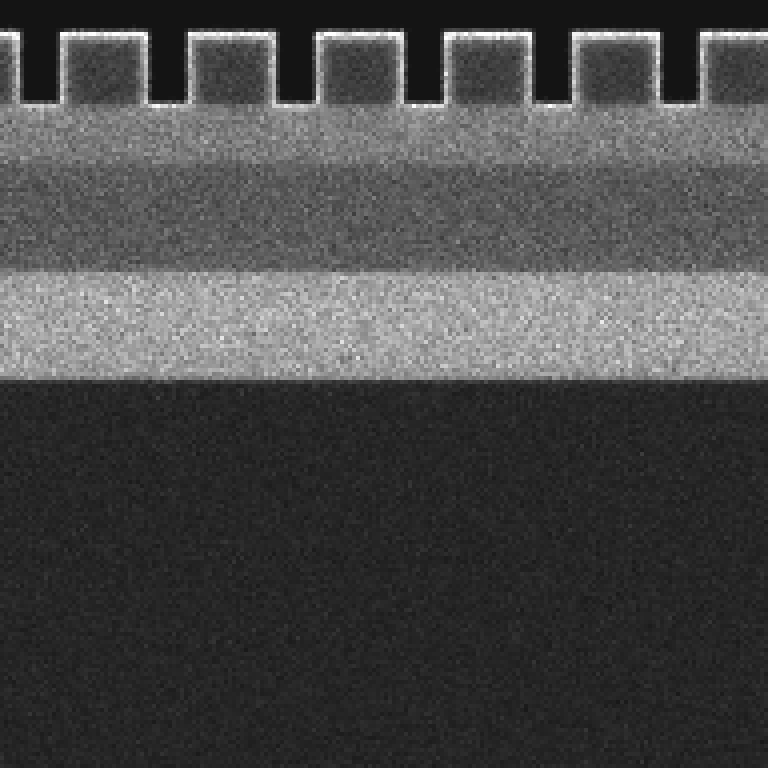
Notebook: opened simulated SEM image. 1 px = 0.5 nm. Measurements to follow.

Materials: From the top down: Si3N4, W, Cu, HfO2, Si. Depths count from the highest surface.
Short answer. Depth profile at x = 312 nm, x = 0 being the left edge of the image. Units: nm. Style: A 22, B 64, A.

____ Si3N4 36, W 30, Cu 54, HfO2 54, Si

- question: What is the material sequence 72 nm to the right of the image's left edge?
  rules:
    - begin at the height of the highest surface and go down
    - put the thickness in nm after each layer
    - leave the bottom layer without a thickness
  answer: Si3N4 36, W 30, Cu 54, HfO2 54, Si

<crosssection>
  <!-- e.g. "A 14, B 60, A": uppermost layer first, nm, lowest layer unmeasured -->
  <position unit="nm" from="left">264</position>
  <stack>Si3N4 36, W 30, Cu 54, HfO2 54, Si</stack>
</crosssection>